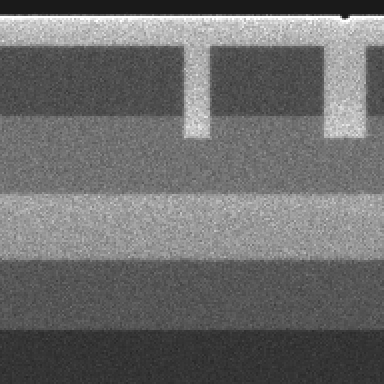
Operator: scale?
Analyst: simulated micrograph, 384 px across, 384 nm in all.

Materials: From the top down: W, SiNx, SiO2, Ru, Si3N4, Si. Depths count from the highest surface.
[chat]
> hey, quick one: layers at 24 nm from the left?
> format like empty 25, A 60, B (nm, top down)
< W 30, SiNx 70, SiO2 78, Ru 66, Si3N4 70, Si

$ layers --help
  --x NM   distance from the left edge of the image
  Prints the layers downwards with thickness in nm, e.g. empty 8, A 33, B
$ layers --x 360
W 122, SiO2 56, Ru 66, Si3N4 70, Si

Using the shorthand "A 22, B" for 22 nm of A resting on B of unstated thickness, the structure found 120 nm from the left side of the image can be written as W 30, SiNx 70, SiO2 78, Ru 66, Si3N4 70, Si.